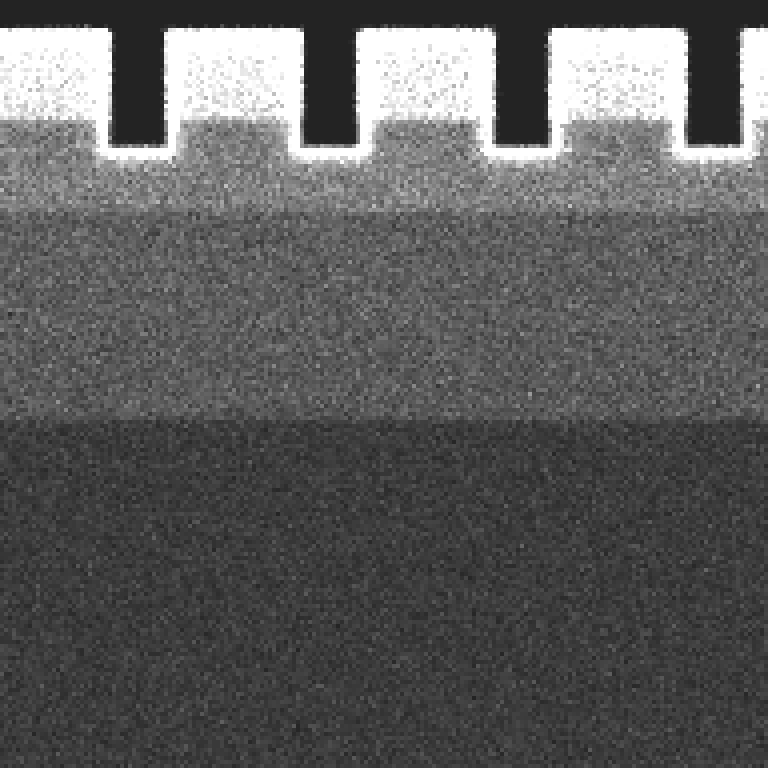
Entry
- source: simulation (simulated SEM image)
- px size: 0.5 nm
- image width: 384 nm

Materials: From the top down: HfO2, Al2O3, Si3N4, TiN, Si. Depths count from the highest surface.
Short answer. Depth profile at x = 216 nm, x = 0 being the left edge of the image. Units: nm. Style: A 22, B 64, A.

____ HfO2 44, Al2O3 46, Si3N4 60, TiN 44, Si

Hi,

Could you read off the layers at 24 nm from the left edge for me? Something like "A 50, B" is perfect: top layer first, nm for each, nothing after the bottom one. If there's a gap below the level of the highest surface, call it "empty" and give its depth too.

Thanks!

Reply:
HfO2 44, Al2O3 46, Si3N4 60, TiN 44, Si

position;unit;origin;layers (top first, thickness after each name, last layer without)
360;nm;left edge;empty 58, Al2O3 32, Si3N4 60, TiN 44, Si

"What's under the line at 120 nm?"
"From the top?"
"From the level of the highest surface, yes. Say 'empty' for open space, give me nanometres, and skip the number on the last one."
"HfO2 44, Al2O3 46, Si3N4 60, TiN 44, Si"